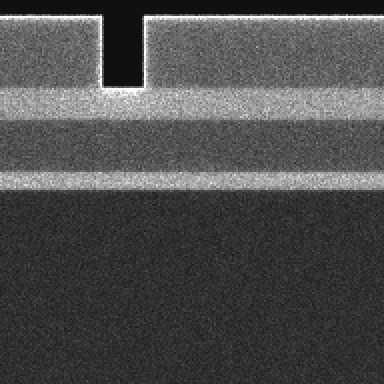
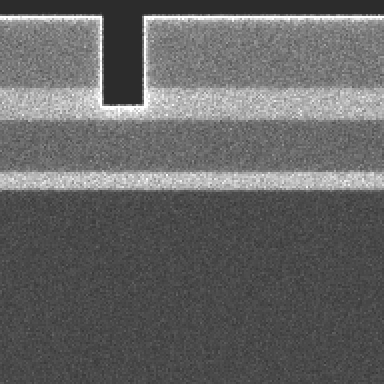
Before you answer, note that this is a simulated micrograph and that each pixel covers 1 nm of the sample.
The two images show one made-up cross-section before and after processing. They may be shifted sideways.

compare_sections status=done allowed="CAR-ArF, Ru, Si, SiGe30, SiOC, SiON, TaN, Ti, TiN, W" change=removed material="Ru"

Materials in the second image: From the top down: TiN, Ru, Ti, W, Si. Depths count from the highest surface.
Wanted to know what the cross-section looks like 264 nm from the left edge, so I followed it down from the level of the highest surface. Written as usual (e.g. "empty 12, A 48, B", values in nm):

TiN 72, Ru 32, Ti 52, W 18, Si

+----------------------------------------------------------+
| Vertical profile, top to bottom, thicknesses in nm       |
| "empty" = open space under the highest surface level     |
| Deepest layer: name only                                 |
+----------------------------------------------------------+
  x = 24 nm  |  TiN 72, Ru 32, Ti 52, W 18, Si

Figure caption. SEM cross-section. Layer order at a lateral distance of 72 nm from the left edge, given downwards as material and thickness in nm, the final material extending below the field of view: TiN 72, Ru 32, Ti 52, W 18, Si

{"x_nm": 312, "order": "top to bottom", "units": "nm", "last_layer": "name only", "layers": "TiN 72, Ru 32, Ti 52, W 18, Si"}